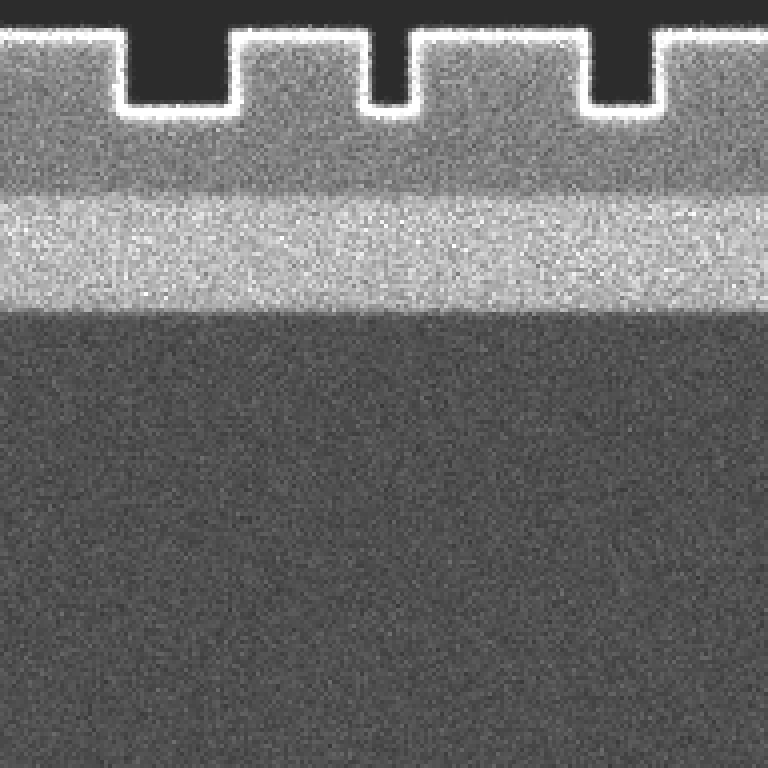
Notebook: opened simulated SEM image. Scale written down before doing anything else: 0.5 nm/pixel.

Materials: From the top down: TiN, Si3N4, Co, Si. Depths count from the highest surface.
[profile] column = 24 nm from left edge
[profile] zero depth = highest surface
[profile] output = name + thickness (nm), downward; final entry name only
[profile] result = TiN 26, Si3N4 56, Co 58, Si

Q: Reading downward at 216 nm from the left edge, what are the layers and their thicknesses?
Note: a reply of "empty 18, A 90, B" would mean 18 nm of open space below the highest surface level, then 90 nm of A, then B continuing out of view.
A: TiN 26, Si3N4 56, Co 58, Si